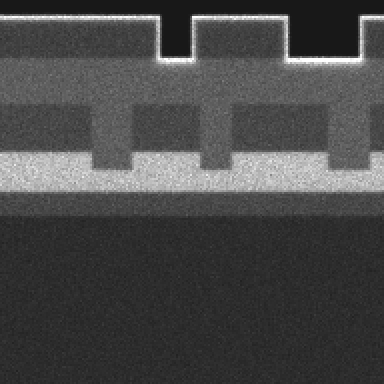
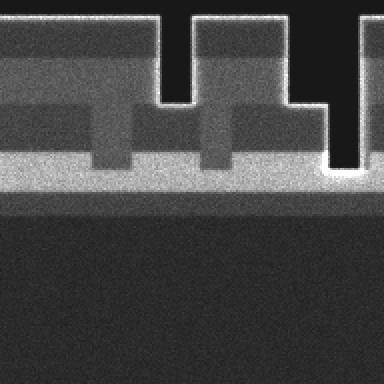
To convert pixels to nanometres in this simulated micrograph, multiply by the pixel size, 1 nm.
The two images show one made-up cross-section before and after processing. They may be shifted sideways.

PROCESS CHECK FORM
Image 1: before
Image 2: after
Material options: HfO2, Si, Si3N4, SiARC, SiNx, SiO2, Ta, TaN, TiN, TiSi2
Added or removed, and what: removed, SiO2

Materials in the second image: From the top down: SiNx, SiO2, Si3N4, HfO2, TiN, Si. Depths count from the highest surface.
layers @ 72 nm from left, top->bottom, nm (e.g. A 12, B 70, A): SiNx 42, SiO2 46, Si3N4 48, HfO2 40, TiN 24, Si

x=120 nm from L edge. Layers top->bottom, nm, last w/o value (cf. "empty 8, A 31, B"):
SiNx 42, SiO2 112, HfO2 22, TiN 24, Si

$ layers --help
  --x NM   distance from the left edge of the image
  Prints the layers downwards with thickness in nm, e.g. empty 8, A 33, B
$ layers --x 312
empty 88, Si3N4 48, HfO2 40, TiN 24, Si